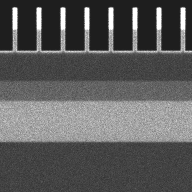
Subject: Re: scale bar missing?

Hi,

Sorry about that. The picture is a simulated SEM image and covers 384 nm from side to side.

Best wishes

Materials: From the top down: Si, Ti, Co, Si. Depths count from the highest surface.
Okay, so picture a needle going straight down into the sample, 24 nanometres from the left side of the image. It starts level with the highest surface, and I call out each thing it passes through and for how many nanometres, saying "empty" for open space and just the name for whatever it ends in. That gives empty 86, Si 60, Ti 40, Co 82, Si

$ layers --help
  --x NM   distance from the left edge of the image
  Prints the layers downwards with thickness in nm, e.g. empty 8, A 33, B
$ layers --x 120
empty 86, Si 60, Ti 40, Co 82, Si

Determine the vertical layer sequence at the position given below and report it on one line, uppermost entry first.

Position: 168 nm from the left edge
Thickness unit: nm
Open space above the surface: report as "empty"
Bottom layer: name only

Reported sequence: empty 86, Si 60, Ti 40, Co 82, Si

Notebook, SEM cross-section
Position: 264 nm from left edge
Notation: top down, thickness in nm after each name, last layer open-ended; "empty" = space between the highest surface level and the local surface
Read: empty 86, Si 60, Ti 40, Co 82, Si